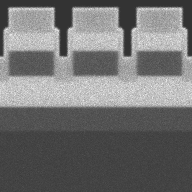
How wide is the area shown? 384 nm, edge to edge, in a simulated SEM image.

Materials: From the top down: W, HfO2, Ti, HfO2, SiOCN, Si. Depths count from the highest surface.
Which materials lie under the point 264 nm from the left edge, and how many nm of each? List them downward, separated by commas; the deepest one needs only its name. empty 44, W 104, HfO2 50, SiOCN 48, Si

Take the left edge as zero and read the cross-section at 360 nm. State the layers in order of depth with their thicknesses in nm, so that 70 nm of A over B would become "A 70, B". W 50, HfO2 36, Ti 50, HfO2 62, SiOCN 48, Si